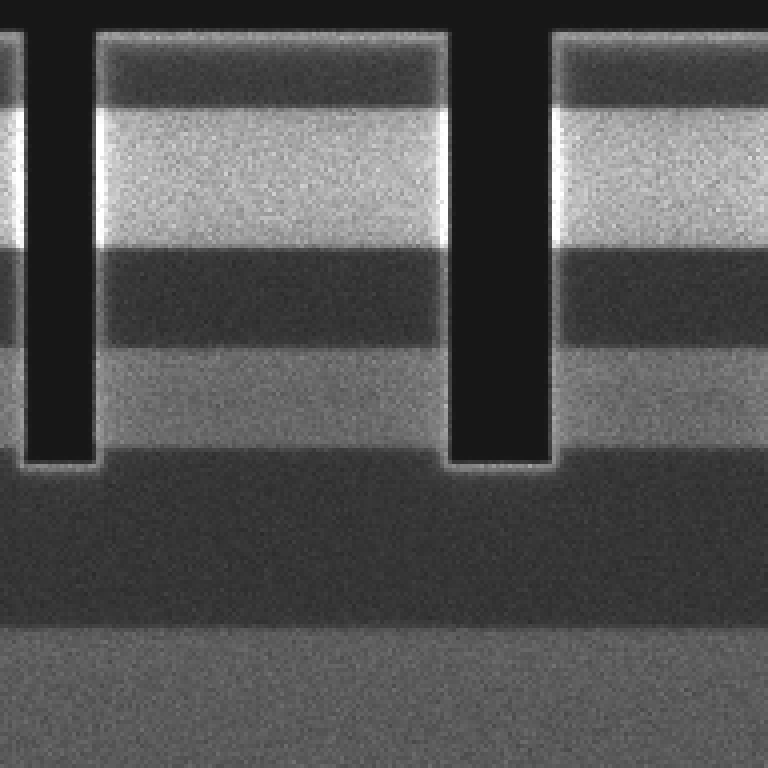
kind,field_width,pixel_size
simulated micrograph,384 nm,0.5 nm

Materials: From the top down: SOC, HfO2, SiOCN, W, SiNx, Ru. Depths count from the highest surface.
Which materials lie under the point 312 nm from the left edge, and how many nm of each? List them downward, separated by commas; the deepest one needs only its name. SOC 38, HfO2 70, SiOCN 50, W 50, SiNx 90, Ru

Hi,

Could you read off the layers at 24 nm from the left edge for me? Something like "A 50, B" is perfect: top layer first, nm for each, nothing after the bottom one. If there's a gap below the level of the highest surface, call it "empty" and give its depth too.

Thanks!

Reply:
empty 216, SiNx 82, Ru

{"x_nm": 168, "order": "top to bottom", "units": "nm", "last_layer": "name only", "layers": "SOC 38, HfO2 70, SiOCN 50, W 50, SiNx 90, Ru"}